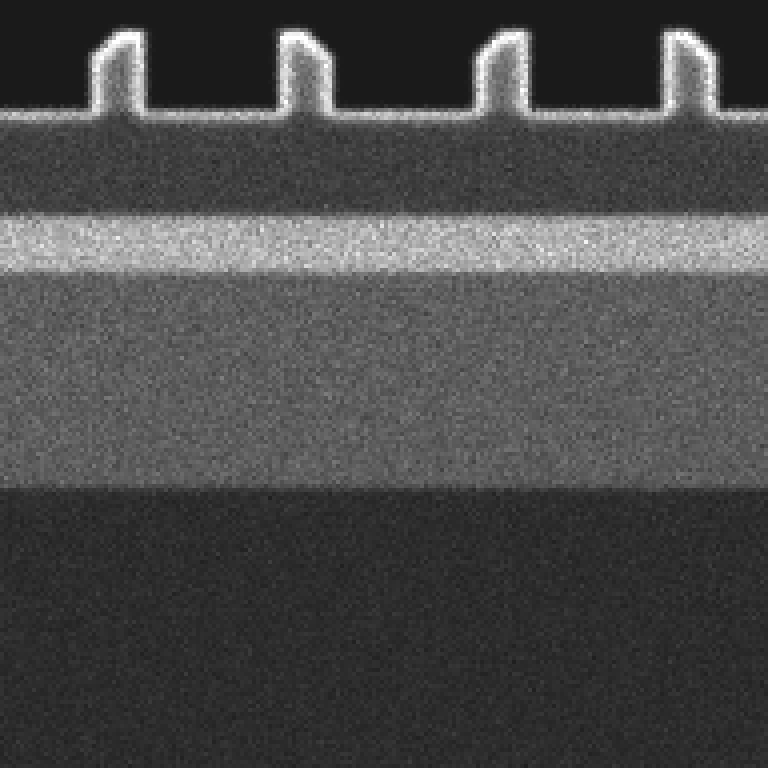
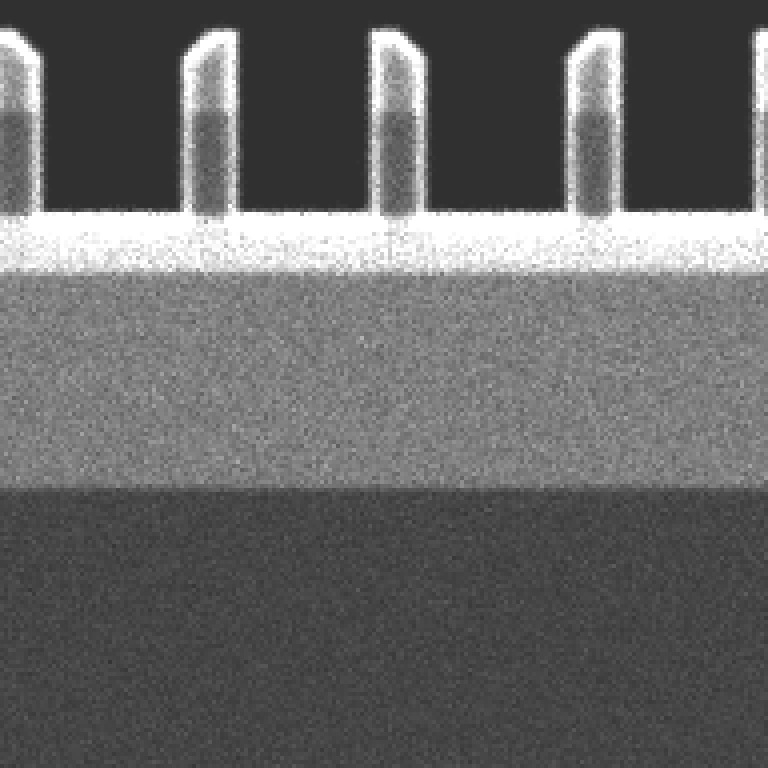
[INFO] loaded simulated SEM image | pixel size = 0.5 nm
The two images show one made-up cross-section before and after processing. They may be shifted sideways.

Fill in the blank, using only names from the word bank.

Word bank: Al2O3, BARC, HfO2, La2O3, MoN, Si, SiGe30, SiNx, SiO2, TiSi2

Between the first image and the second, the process removed SiNx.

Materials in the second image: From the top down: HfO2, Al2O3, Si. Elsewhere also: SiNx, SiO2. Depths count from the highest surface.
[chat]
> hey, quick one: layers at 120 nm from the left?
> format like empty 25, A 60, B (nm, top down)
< empty 92, HfO2 28, Al2O3 108, Si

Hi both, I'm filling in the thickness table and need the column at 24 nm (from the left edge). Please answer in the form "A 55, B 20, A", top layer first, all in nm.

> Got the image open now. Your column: empty 92, HfO2 28, Al2O3 108, Si